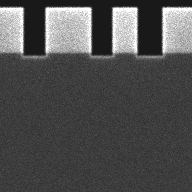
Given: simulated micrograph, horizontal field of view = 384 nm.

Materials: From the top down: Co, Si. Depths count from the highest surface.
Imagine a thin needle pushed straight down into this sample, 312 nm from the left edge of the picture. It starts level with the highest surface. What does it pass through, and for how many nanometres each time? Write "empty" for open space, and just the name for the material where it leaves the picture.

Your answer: empty 96, Si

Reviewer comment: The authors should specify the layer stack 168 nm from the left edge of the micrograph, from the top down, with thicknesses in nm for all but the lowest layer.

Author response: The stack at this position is Co 90, Si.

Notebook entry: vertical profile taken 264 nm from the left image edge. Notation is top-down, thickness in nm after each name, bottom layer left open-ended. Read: Co 90, Si